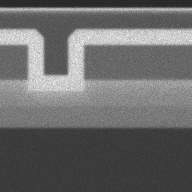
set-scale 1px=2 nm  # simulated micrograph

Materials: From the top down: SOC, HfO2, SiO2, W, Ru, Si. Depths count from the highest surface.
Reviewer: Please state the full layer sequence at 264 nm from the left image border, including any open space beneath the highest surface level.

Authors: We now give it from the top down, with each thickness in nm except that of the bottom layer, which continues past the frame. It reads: SOC 42, HfO2 32, SiO2 70, W 52, Ru 44, Si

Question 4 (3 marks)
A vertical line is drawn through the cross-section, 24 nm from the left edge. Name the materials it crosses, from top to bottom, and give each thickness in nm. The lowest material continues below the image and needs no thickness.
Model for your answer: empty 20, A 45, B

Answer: SOC 42, HfO2 32, SiO2 70, W 52, Ru 44, Si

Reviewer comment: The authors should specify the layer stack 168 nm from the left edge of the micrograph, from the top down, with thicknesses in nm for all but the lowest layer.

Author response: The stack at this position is SOC 42, HfO2 32, SiO2 70, W 52, Ru 44, Si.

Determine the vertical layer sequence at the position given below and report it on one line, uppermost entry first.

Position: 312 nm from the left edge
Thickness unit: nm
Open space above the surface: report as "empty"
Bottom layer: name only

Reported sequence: SOC 42, HfO2 32, SiO2 70, W 52, Ru 44, Si